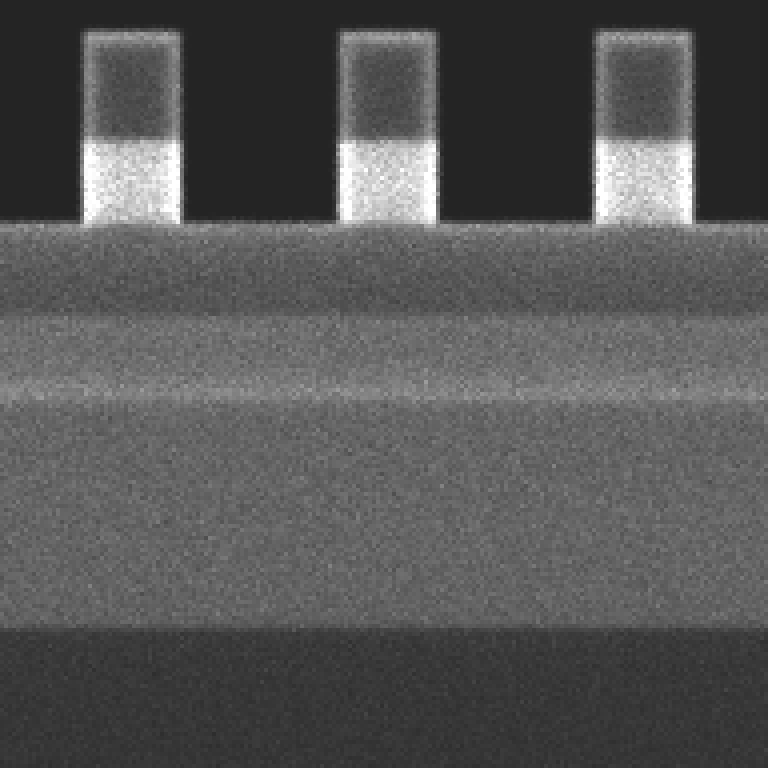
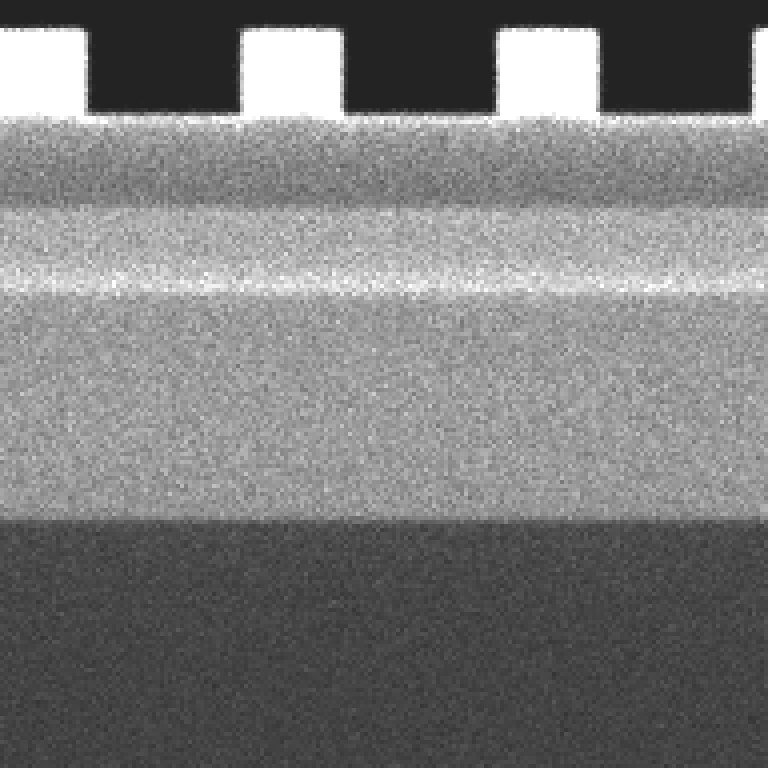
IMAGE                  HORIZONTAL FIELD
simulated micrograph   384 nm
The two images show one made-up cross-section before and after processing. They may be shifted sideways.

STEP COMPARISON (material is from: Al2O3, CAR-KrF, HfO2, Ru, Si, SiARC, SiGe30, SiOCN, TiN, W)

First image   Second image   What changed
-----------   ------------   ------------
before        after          SiARC, removed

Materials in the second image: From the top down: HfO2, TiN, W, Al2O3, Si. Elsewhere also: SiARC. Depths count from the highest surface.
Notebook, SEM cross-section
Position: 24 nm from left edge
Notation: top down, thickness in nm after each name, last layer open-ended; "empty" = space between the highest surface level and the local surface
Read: HfO2 42, TiN 46, W 42, Al2O3 114, Si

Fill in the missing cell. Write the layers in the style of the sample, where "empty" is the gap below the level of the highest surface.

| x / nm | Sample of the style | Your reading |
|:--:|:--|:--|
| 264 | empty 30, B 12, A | HfO2 42, TiN 46, W 42, Al2O3 114, Si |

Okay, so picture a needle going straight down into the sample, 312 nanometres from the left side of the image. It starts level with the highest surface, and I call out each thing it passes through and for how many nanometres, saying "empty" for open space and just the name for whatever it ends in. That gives empty 42, TiN 46, W 42, Al2O3 114, Si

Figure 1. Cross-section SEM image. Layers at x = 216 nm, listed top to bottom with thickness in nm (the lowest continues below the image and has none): empty 42, TiN 46, W 42, Al2O3 114, Si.